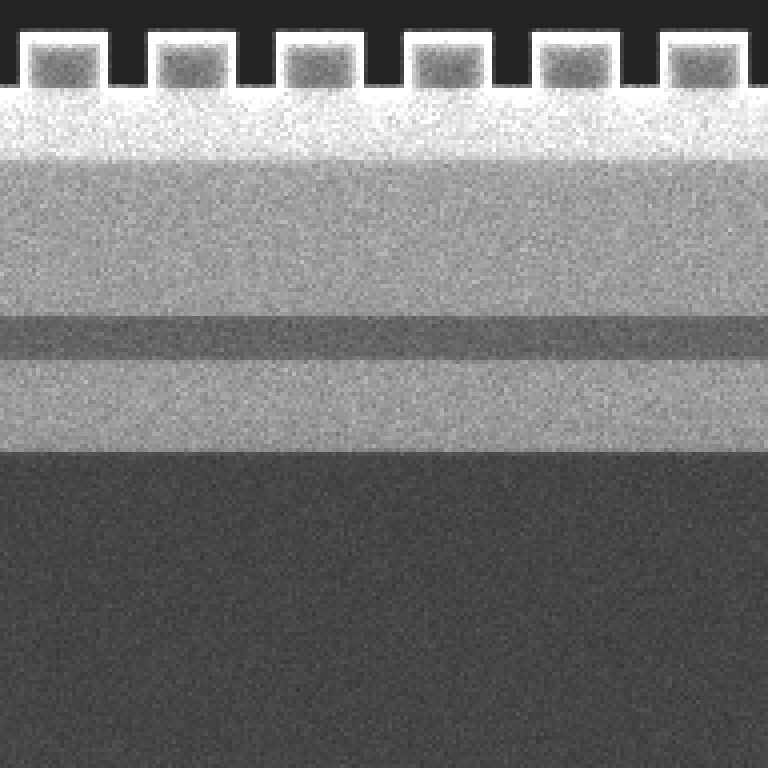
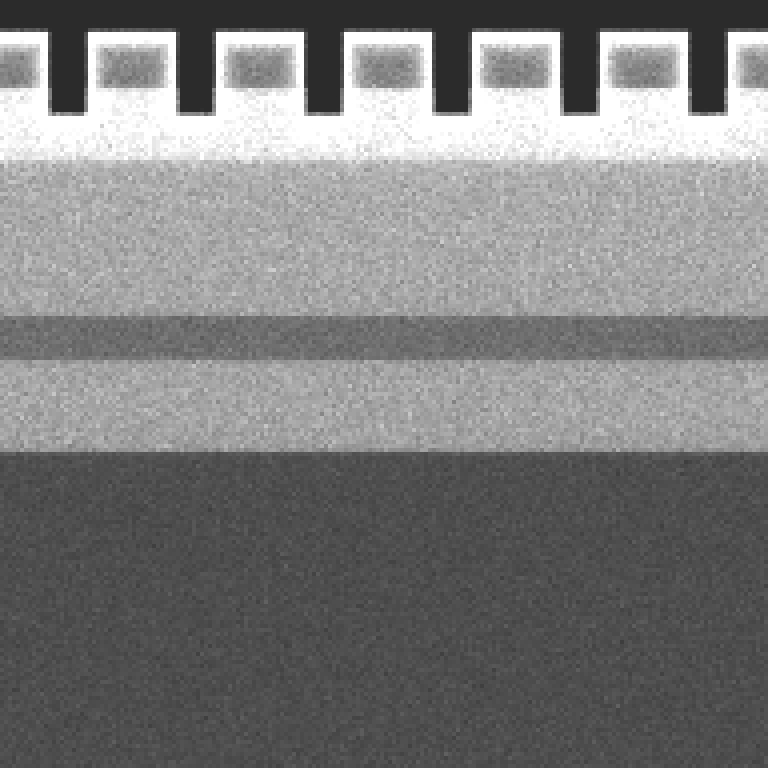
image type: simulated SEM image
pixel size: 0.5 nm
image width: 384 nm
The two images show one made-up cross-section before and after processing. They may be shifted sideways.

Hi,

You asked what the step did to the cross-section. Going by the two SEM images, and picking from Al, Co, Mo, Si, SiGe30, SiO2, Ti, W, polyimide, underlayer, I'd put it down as W, removed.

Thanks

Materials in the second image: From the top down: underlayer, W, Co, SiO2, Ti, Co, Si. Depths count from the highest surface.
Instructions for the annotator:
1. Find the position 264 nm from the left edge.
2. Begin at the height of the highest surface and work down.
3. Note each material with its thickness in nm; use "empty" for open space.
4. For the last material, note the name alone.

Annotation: underlayer 28, W 36, Co 68, SiO2 10, Ti 22, Co 46, Si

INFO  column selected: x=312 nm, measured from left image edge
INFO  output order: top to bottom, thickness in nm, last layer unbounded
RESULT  underlayer 28, W 36, Co 68, SiO2 10, Ti 22, Co 46, Si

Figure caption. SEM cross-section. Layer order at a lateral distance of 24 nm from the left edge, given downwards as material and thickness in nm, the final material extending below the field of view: empty 42, W 22, Co 68, SiO2 10, Ti 22, Co 46, Si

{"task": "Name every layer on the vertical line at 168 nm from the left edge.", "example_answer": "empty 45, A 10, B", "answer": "empty 42, W 22, Co 68, SiO2 10, Ti 22, Co 46, Si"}